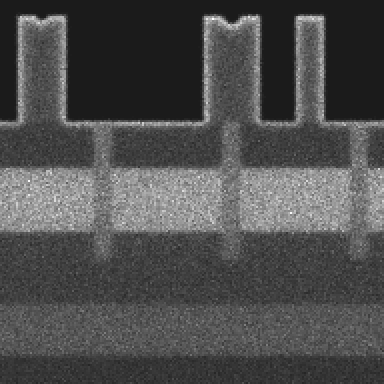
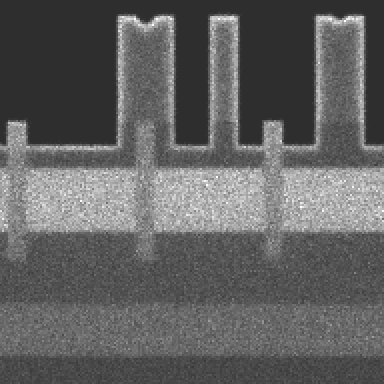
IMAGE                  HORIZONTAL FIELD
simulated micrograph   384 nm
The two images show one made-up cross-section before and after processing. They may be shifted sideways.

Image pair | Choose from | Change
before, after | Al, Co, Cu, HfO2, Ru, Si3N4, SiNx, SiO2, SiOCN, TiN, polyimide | Si3N4 (removed)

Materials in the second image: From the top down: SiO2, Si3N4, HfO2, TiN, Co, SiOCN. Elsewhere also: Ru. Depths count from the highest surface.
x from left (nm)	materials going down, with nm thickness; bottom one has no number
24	empty 106, Ru 138, TiN 44, Co 52, SiOCN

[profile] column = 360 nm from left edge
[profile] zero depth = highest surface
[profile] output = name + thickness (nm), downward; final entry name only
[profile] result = SiO2 106, Si3N4 46, HfO2 64, TiN 72, Co 52, SiOCN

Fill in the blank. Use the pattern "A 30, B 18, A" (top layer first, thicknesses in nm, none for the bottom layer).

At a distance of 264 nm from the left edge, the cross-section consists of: empty 106, Ru 138, TiN 44, Co 52, SiOCN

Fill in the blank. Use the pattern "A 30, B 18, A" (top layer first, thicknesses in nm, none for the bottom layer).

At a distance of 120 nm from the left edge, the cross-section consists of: SiO2 106, Si3N4 46, HfO2 64, TiN 72, Co 52, SiOCN